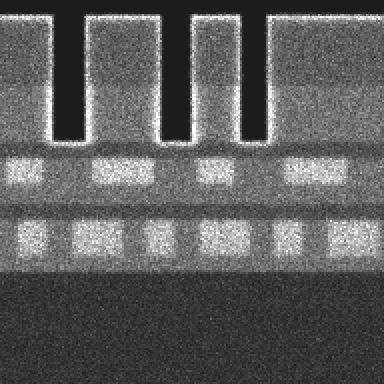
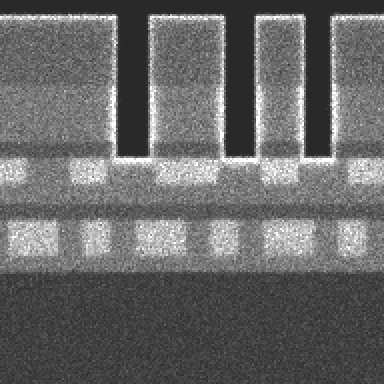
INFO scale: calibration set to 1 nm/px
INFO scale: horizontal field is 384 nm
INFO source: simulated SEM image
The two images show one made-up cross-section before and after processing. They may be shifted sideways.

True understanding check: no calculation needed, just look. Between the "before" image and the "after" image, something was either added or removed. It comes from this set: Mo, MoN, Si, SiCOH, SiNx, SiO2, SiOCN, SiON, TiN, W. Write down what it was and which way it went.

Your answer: SiNx (removed)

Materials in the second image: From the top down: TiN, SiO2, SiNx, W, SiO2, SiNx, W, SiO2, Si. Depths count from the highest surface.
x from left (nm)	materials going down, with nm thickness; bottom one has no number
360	TiN 70, SiO2 56, SiNx 16, W 26, SiO2 20, SiNx 16, W 36, SiO2 16, Si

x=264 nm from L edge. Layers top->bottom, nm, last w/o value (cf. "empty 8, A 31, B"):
TiN 70, SiO2 56, SiNx 16, W 26, SiO2 20, SiNx 16, W 36, SiO2 16, Si